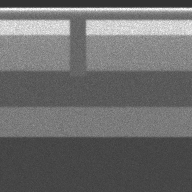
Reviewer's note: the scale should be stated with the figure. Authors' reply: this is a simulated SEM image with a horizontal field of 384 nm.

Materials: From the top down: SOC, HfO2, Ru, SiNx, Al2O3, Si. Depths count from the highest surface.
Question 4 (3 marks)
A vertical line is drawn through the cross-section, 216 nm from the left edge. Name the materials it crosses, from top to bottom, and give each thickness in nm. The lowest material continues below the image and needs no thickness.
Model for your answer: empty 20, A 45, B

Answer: SOC 24, HfO2 30, Ru 72, SiNx 72, Al2O3 60, Si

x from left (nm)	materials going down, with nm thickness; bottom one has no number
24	SOC 24, HfO2 30, Ru 72, SiNx 72, Al2O3 60, Si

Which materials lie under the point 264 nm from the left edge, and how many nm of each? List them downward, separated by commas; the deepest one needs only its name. SOC 24, HfO2 30, Ru 72, SiNx 72, Al2O3 60, Si